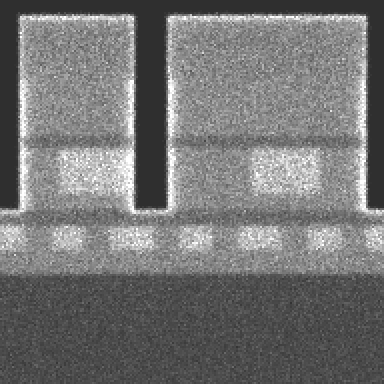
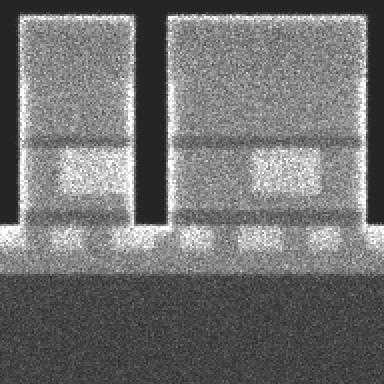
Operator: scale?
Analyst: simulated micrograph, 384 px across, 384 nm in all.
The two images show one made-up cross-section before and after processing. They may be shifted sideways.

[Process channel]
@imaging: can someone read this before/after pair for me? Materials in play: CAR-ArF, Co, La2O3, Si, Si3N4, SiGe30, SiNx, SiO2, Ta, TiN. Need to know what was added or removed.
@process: SiNx removed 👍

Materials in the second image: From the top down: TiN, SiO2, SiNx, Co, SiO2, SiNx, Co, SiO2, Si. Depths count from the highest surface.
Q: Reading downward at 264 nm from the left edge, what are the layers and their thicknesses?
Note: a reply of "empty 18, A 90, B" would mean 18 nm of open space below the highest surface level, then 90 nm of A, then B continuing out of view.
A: TiN 64, SiO2 56, SiNx 12, Co 46, SiO2 16, SiNx 16, Co 24, SiO2 24, Si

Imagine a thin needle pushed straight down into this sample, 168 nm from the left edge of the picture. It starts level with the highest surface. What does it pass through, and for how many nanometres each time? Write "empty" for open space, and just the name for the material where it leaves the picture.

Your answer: TiN 64, SiO2 56, SiNx 12, SiO2 62, SiNx 16, SiO2 48, Si